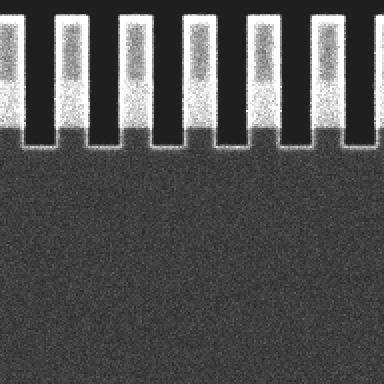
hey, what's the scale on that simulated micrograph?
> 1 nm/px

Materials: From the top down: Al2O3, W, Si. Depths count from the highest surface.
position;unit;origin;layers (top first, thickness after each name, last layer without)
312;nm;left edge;Al2O3 64, W 48, Si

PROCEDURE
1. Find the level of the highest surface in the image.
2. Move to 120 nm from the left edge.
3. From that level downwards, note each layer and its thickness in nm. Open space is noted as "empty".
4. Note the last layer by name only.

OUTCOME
Al2O3 64, W 48, Si